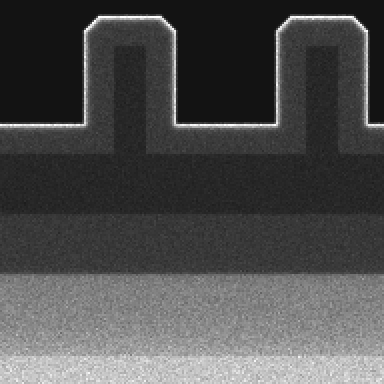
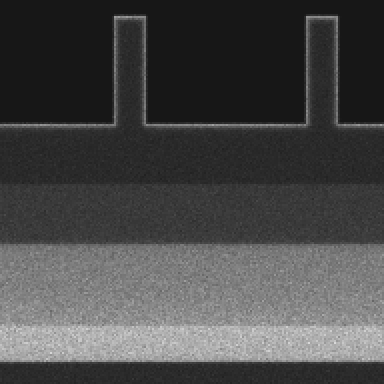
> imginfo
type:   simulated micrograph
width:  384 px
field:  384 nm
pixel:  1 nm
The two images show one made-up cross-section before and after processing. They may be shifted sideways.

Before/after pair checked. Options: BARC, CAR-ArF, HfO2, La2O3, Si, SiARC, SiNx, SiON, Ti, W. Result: removed SiNx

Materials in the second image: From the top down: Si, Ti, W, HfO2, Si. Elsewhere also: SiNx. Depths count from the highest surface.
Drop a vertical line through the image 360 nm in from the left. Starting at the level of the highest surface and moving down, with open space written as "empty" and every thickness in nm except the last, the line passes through empty 108, Si 60, Ti 60, W 82, HfO2 36, Si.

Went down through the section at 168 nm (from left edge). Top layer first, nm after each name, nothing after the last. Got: empty 108, Si 60, Ti 60, W 82, HfO2 36, Si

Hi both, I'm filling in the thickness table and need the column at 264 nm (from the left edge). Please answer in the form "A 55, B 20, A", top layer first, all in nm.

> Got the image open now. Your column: empty 108, Si 60, Ti 60, W 82, HfO2 36, Si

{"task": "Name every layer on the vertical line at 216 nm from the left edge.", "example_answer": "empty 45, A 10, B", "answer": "empty 108, Si 60, Ti 60, W 82, HfO2 36, Si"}